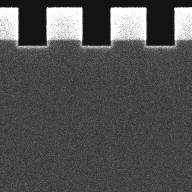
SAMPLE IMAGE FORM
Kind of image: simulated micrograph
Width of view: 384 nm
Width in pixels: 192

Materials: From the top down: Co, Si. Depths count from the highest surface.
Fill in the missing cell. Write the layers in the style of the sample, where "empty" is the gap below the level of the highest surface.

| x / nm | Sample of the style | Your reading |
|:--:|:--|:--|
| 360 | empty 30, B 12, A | Co 64, Si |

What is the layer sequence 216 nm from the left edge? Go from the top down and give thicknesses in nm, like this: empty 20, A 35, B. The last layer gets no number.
empty 76, Si